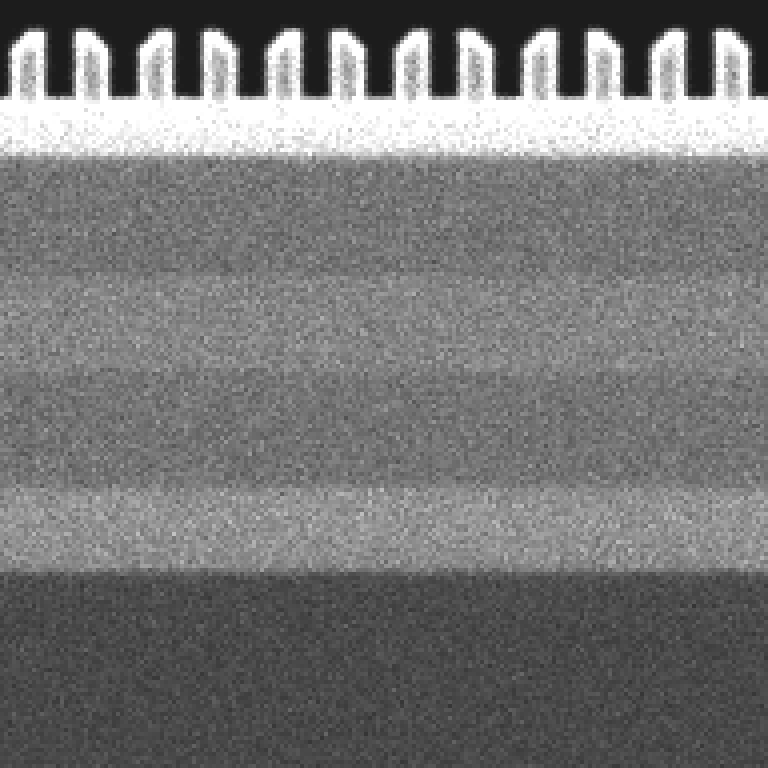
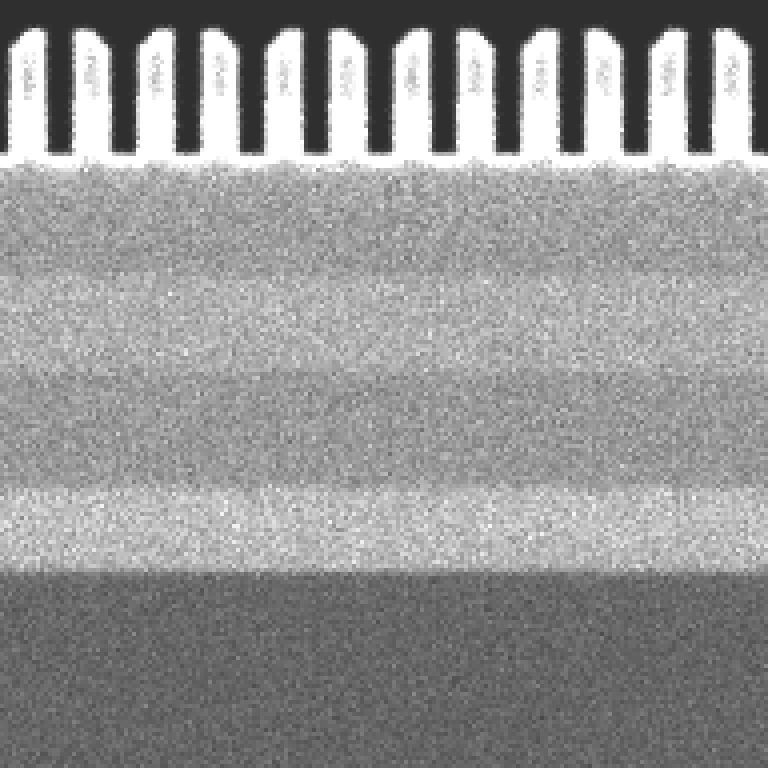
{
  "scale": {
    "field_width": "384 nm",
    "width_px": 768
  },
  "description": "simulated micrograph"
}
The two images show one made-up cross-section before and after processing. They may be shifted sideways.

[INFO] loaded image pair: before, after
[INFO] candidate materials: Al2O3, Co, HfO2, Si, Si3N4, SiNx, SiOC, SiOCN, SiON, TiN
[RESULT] removed Co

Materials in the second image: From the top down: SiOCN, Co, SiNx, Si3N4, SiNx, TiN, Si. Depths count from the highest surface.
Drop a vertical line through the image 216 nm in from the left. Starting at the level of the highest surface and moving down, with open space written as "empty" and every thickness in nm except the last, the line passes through empty 62, SiNx 60, Si3N4 48, SiNx 58, TiN 42, Si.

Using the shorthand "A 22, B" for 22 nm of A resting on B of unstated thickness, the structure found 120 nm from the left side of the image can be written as empty 62, SiNx 60, Si3N4 48, SiNx 58, TiN 42, Si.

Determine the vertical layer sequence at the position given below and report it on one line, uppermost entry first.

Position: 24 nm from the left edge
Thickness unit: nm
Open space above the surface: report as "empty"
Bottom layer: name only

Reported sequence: empty 62, SiNx 60, Si3N4 48, SiNx 58, TiN 42, Si